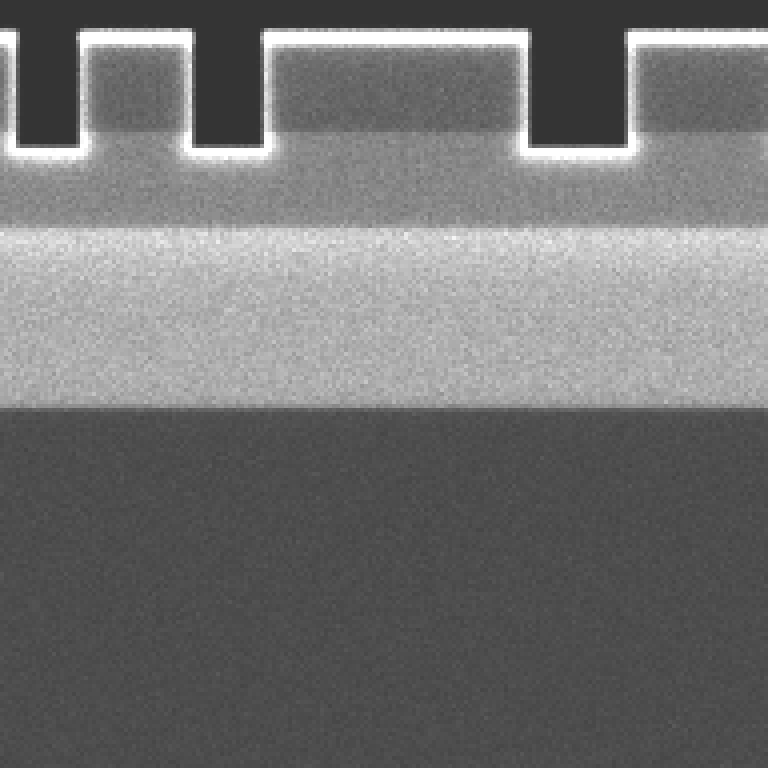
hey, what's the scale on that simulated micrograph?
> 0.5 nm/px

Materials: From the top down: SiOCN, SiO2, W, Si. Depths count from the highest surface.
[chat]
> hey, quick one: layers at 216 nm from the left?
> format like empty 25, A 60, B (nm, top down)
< SiOCN 50, SiO2 48, W 90, Si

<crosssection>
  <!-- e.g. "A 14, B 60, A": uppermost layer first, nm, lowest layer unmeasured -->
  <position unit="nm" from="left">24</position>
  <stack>empty 58, SiO2 40, W 90, Si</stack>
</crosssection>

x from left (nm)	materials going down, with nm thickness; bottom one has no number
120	empty 58, SiO2 40, W 90, Si